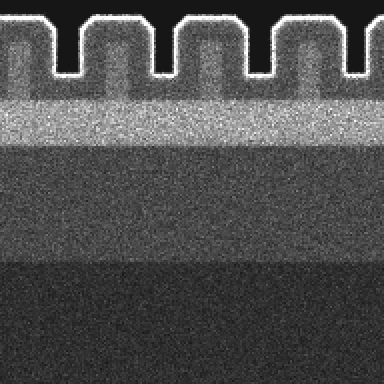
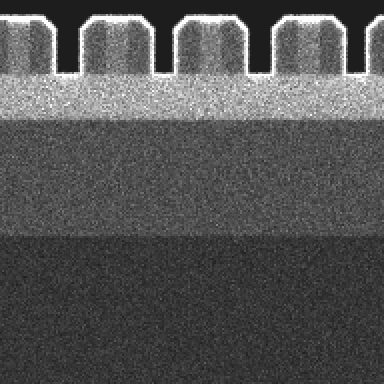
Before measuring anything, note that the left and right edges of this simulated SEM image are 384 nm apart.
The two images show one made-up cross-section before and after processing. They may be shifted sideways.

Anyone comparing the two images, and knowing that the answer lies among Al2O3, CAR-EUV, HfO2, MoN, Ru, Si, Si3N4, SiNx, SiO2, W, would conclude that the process removed Si3N4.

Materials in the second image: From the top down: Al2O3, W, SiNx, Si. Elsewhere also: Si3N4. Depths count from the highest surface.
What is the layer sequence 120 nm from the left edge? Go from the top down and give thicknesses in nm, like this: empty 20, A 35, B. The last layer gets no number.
Al2O3 58, W 46, SiNx 116, Si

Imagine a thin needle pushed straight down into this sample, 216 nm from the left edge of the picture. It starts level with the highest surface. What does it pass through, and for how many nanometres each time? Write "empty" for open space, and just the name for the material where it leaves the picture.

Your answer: Al2O3 58, W 46, SiNx 116, Si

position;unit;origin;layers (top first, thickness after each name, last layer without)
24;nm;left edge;Al2O3 58, W 46, SiNx 116, Si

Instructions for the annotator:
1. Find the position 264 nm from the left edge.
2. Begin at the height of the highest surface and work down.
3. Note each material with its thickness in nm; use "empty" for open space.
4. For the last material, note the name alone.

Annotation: empty 58, W 46, SiNx 116, Si